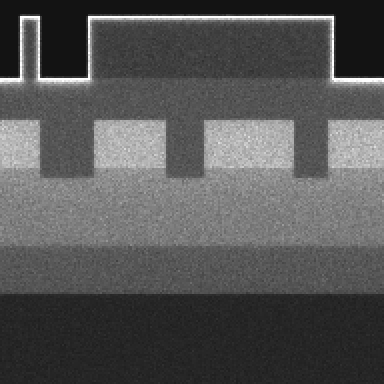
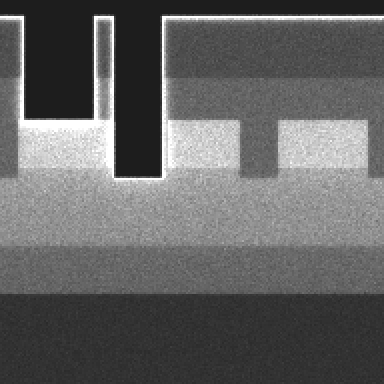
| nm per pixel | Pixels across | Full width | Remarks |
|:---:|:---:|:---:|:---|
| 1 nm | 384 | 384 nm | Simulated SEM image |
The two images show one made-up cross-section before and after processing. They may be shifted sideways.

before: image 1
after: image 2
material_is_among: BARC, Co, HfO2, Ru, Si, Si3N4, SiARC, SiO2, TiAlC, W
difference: SiO2, removed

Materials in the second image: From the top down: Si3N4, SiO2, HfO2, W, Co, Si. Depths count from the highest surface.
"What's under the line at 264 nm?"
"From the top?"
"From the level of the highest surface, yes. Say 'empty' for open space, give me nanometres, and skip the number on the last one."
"Si3N4 62, SiO2 100, W 68, Co 48, Si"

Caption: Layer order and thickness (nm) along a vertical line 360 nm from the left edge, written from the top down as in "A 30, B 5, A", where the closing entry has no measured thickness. Si3N4 62, SiO2 42, HfO2 48, W 78, Co 48, Si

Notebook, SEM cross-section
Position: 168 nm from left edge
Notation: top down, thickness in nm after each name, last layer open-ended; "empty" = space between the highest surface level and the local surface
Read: Si3N4 62, SiO2 42, HfO2 48, W 78, Co 48, Si